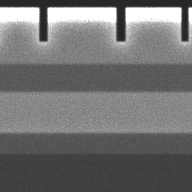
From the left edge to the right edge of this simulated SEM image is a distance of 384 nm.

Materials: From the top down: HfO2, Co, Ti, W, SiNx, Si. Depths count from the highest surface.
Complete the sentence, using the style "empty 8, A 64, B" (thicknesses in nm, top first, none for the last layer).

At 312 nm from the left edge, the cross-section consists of HfO2 28, Co 84, Ti 56, W 82, SiNx 42, Si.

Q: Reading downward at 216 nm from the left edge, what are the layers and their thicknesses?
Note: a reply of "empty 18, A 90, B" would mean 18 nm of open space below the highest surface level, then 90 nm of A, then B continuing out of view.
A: HfO2 28, Co 84, Ti 56, W 82, SiNx 42, Si